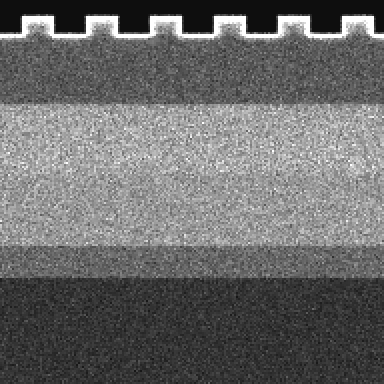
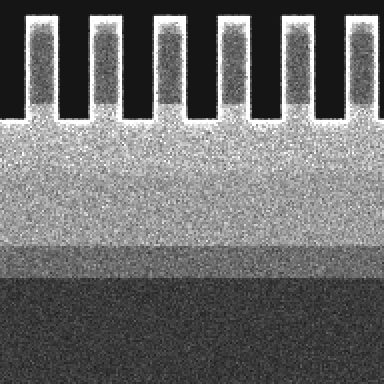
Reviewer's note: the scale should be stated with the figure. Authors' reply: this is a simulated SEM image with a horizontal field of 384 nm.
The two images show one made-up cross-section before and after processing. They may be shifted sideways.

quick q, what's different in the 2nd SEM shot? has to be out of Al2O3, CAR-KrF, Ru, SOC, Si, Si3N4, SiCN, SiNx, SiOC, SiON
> Ru and SiNx removed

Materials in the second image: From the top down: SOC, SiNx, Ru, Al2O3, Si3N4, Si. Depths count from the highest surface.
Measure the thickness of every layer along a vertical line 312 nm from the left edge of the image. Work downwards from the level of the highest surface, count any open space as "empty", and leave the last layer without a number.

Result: SOC 18, SiNx 70, Ru 70, Al2O3 72, Si3N4 32, Si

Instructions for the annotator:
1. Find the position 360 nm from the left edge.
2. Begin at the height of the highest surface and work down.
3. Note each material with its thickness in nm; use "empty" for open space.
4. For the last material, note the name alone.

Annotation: SOC 18, SiNx 70, Ru 70, Al2O3 72, Si3N4 32, Si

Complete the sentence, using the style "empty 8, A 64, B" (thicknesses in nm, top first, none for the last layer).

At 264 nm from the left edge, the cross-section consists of empty 104, Ru 54, Al2O3 72, Si3N4 32, Si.